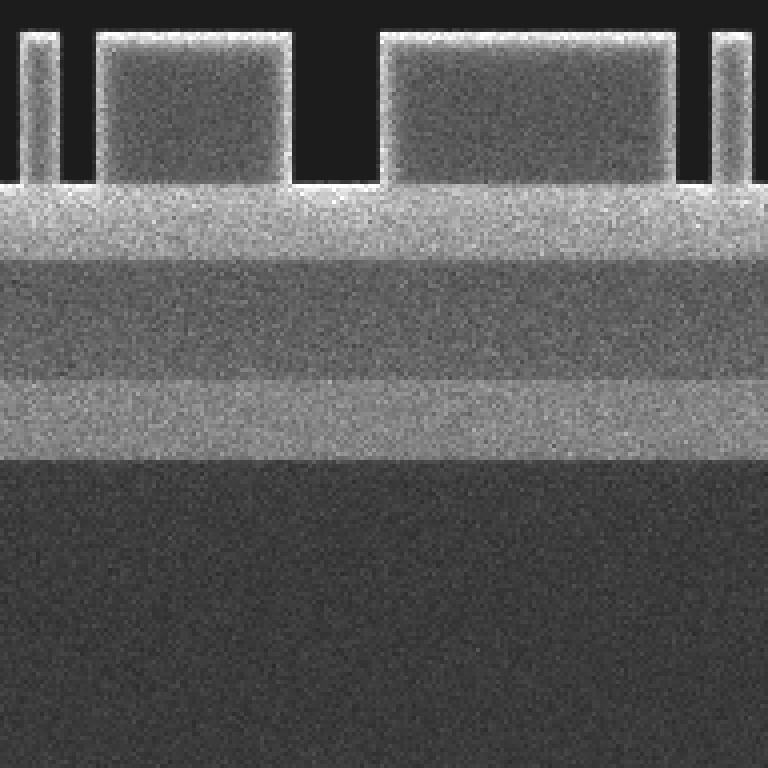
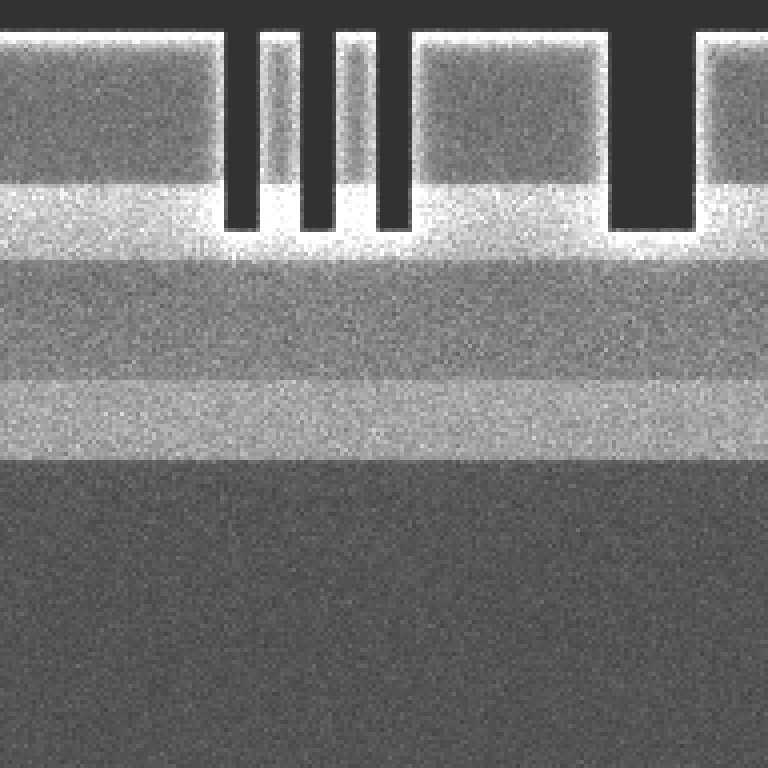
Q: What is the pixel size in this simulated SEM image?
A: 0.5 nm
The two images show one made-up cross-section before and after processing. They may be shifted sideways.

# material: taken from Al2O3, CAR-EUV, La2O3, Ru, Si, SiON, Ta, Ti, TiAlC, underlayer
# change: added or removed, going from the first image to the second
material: Ru
change: removed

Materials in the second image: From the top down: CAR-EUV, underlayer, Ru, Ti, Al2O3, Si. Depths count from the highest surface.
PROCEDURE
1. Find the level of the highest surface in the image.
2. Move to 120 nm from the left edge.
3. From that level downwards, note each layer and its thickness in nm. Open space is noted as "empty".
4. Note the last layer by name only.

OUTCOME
empty 100, Ru 14, Ti 60, Al2O3 40, Si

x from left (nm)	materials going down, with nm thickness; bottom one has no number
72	CAR-EUV 54, underlayer 22, Ru 38, Ti 60, Al2O3 40, Si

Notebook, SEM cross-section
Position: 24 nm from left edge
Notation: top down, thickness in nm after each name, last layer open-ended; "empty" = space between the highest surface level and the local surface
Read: CAR-EUV 54, underlayer 22, Ru 38, Ti 60, Al2O3 40, Si